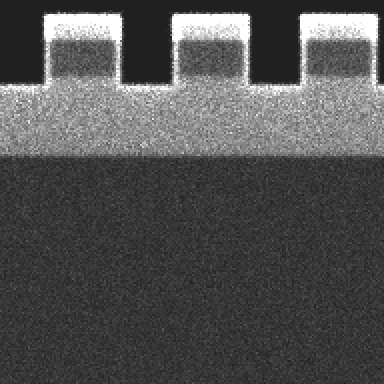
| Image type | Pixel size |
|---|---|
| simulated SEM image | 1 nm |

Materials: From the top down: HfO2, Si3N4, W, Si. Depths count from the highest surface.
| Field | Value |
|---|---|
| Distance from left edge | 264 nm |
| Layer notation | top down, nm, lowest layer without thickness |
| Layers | empty 70, W 70, Si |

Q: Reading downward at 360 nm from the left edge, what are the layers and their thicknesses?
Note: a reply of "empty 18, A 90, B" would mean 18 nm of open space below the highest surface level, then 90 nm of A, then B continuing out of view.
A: HfO2 24, Si3N4 36, W 80, Si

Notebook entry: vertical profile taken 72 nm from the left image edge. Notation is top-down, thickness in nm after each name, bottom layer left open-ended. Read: HfO2 24, Si3N4 36, W 80, Si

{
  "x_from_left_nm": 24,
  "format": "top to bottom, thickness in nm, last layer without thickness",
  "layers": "empty 70, W 70, Si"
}